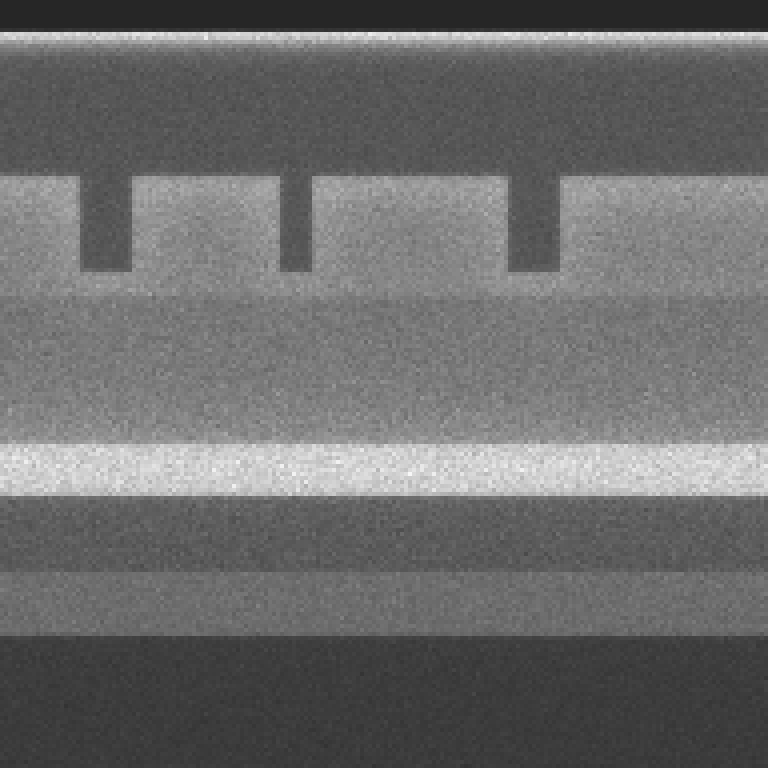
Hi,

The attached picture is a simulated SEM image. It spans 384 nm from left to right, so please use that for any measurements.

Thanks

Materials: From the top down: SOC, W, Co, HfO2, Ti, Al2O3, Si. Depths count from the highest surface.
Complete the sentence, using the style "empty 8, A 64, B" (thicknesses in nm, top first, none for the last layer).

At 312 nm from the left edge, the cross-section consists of SOC 72, W 60, Co 74, HfO2 26, Ti 38, Al2O3 32, Si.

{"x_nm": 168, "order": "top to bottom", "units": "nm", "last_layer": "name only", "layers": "SOC 72, W 60, Co 74, HfO2 26, Ti 38, Al2O3 32, Si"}